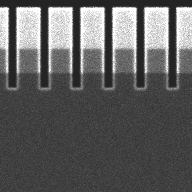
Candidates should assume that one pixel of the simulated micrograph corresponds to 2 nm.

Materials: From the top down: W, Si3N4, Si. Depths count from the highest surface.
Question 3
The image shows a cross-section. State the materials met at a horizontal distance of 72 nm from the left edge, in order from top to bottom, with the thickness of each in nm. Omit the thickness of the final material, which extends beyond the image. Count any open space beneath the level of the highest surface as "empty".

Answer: W 82, Si3N4 48, Si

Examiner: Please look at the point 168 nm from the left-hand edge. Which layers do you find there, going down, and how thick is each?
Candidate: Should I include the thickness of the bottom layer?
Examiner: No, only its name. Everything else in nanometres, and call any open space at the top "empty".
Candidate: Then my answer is W 82, Si3N4 48, Si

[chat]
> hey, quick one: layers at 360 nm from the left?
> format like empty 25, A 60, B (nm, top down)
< W 82, Si3N4 48, Si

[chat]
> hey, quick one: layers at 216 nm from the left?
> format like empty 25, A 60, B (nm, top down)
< empty 160, Si